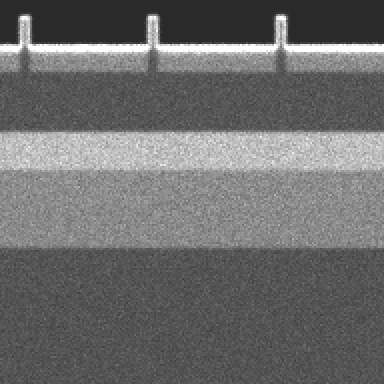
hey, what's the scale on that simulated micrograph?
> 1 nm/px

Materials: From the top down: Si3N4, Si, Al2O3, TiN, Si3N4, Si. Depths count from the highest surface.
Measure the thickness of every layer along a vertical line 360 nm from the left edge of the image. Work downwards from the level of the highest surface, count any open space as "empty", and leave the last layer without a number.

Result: empty 30, Si3N4 26, Si 60, Al2O3 38, TiN 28, Si3N4 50, Si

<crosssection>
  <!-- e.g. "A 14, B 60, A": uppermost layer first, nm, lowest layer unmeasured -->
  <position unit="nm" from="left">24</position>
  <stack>Si 116, Al2O3 38, TiN 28, Si3N4 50, Si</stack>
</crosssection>